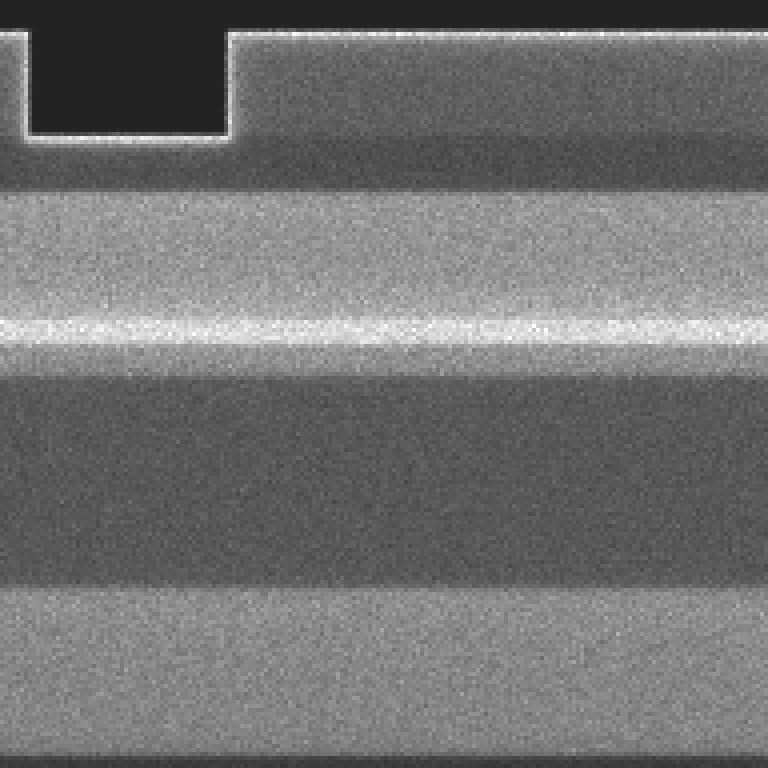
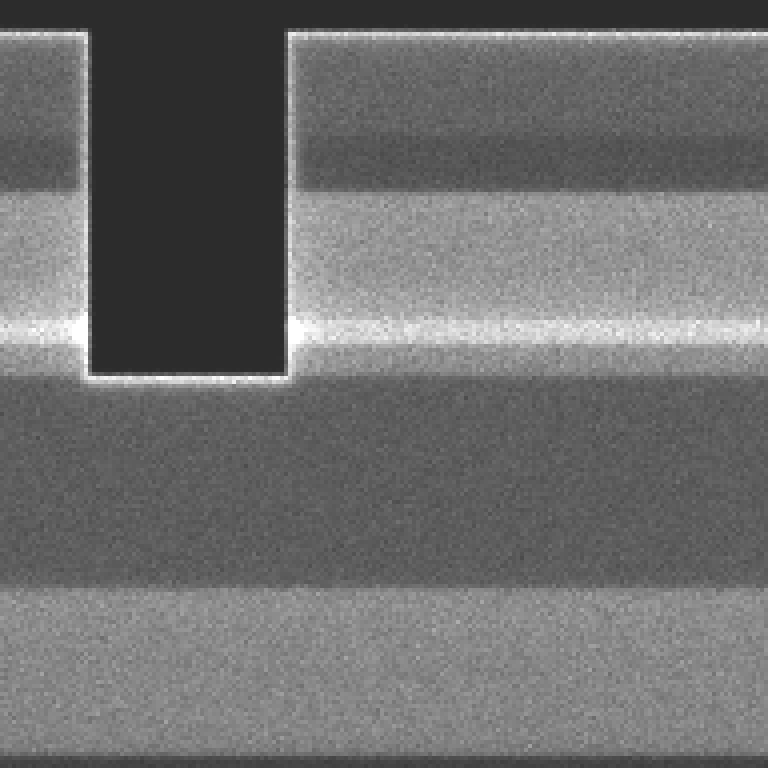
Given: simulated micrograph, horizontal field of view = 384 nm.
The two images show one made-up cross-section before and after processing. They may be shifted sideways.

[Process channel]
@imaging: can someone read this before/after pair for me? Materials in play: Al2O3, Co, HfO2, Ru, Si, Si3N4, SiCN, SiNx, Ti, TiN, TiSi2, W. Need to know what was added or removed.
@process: Co and HfO2 and SiNx and W removed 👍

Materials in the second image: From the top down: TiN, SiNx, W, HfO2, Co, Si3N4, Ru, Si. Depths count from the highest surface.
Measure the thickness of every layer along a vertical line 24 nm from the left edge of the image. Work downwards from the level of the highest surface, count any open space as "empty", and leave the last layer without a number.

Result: TiN 52, SiNx 28, W 64, HfO2 12, Co 16, Si3N4 106, Ru 84, Si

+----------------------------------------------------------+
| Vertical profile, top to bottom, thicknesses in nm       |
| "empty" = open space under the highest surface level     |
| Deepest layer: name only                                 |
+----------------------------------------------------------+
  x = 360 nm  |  TiN 52, SiNx 28, W 64, HfO2 12, Co 16, Si3N4 106, Ru 84, Si